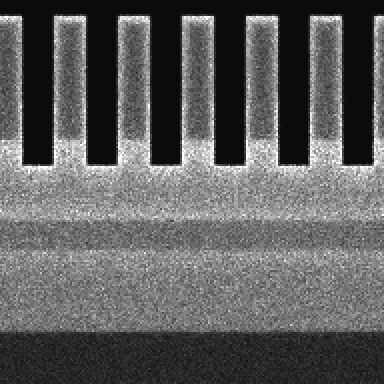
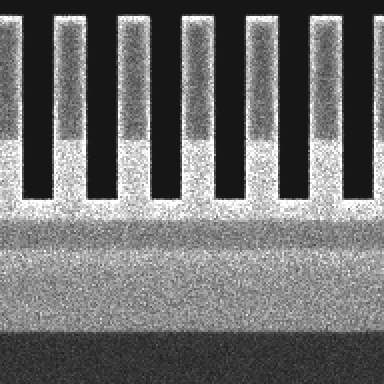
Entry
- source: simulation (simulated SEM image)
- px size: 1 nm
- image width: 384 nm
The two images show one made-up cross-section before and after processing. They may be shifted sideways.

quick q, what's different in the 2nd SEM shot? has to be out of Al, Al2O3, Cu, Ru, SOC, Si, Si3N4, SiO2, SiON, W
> W removed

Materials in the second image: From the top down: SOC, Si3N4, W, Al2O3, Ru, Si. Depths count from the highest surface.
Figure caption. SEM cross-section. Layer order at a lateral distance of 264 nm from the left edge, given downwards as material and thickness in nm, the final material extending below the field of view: SOC 86, Si3N4 38, W 80, Al2O3 30, Ru 82, Si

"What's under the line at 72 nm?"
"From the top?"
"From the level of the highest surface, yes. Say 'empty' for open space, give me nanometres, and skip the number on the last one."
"SOC 86, Si3N4 38, W 80, Al2O3 30, Ru 82, Si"